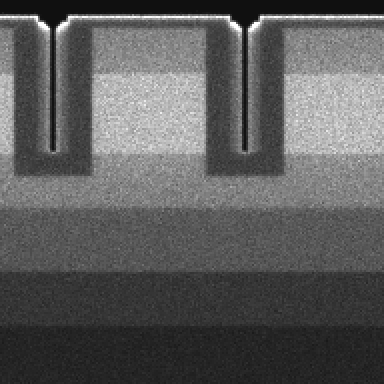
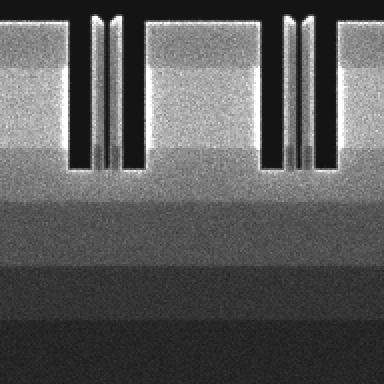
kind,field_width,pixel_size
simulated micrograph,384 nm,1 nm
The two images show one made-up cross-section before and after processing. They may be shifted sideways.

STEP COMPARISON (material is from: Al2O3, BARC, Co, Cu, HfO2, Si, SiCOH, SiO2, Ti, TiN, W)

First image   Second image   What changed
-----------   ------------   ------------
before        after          TiN, removed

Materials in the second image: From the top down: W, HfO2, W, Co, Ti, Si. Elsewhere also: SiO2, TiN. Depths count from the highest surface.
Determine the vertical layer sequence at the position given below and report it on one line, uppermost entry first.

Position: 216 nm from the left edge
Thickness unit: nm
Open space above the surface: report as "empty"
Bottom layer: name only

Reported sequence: empty 6, W 46, HfO2 80, W 54, Co 64, Ti 54, Si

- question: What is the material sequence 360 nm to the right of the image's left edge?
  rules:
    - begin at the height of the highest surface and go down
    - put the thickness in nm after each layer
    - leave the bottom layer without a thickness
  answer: empty 6, W 46, HfO2 80, W 54, Co 64, Ti 54, Si